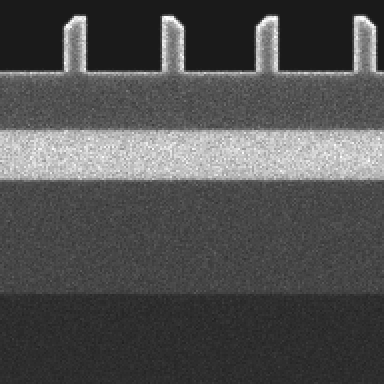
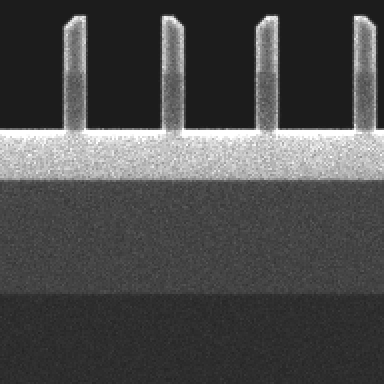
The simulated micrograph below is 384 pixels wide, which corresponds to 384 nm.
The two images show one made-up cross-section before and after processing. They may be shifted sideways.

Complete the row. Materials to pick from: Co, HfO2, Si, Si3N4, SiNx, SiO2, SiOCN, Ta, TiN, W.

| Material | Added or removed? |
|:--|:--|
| TiN | removed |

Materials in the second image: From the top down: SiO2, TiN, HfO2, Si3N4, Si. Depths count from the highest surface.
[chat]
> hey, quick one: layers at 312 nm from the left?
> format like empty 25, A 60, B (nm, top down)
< empty 114, HfO2 50, Si3N4 114, Si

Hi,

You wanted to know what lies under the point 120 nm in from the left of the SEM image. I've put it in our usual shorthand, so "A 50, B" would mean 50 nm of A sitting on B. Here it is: empty 114, HfO2 50, Si3N4 114, Si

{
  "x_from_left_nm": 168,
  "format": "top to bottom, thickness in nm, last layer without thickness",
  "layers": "SiO2 56, TiN 58, HfO2 50, Si3N4 114, Si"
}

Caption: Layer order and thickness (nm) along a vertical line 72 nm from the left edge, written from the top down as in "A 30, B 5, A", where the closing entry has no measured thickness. empty 2, SiO2 54, TiN 58, HfO2 50, Si3N4 114, Si